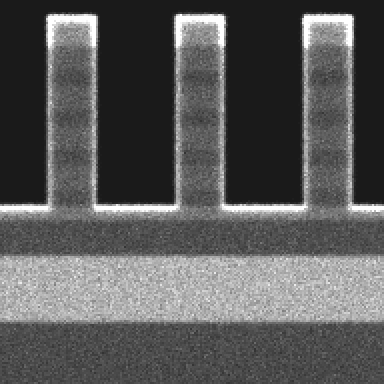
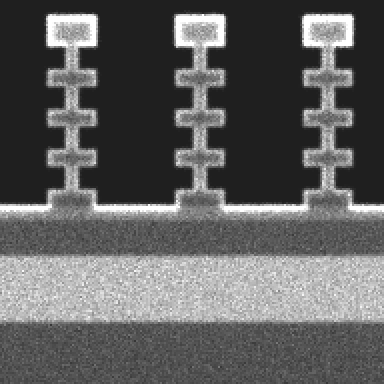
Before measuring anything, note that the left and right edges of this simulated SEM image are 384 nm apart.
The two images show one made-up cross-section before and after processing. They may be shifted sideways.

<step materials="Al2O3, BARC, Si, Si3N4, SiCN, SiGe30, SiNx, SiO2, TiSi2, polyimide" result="removed SiGe30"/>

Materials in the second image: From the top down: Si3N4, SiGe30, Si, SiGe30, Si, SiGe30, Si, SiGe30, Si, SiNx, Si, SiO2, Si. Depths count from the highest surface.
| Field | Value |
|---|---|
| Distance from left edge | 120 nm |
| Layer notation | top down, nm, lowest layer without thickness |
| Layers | empty 190, SiNx 14, Si 36, SiO2 66, Si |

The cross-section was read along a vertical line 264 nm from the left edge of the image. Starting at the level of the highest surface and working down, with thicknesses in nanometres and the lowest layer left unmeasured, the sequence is empty 190, SiNx 14, Si 36, SiO2 66, Si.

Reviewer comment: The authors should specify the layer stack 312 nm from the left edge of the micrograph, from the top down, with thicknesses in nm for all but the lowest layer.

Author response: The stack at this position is Si3N4 30, empty 24, Si 16, empty 24, Si 16, empty 24, Si 16, empty 24, Si 16, SiNx 14, Si 36, SiO2 66, Si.